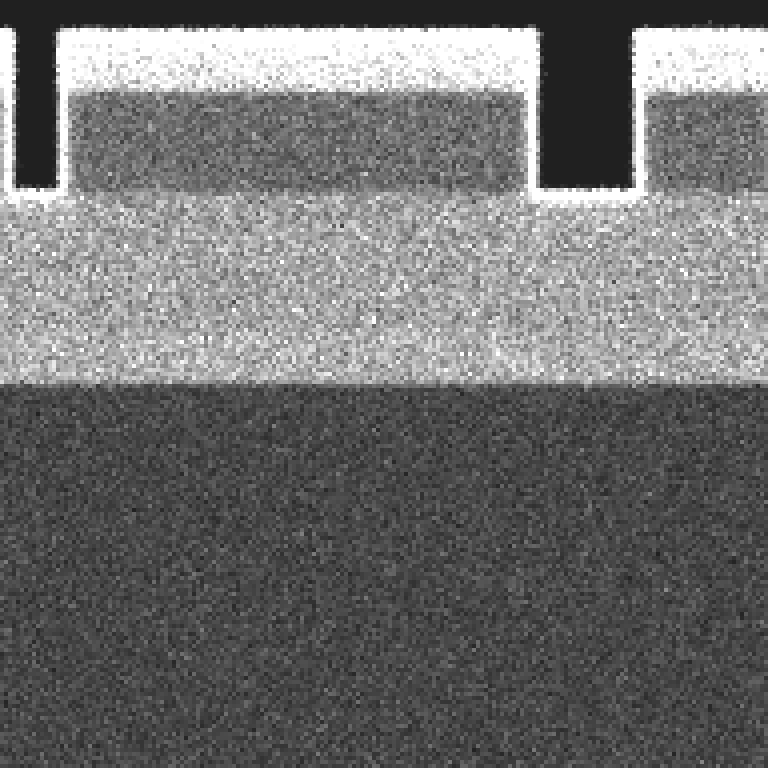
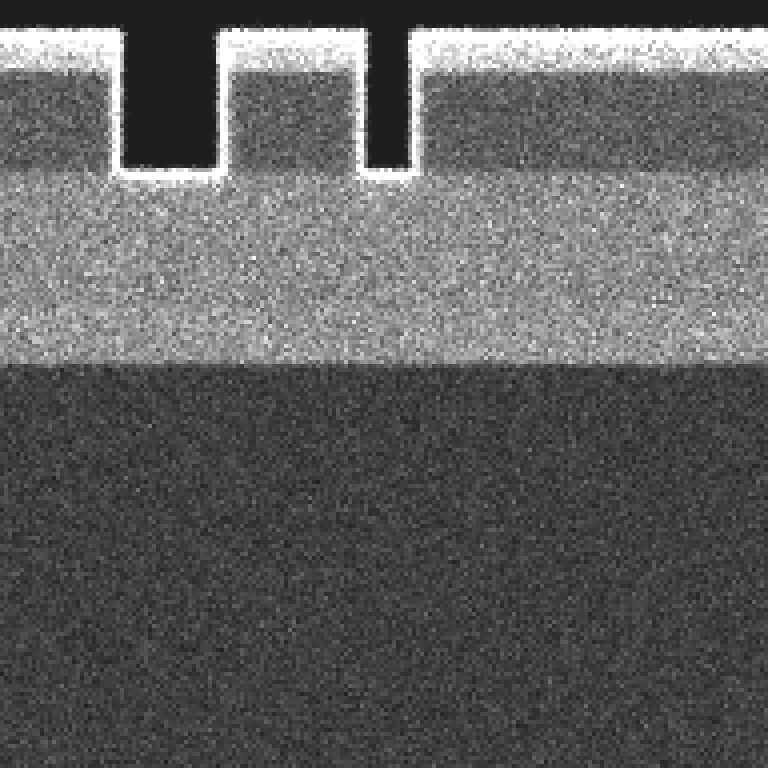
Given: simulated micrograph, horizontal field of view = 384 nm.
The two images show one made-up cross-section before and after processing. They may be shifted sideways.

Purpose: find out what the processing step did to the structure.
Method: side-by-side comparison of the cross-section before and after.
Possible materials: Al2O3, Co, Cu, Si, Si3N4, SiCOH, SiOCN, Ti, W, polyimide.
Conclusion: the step removed W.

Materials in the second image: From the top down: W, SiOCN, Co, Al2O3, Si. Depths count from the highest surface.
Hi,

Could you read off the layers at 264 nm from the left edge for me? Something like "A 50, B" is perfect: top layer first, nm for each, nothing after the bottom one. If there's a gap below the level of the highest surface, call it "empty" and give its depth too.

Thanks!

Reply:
W 20, SiOCN 50, Co 68, Al2O3 28, Si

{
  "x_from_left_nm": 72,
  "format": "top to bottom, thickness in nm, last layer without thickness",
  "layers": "empty 70, Co 68, Al2O3 28, Si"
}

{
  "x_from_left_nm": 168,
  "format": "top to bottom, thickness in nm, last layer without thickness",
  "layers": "W 20, SiOCN 50, Co 68, Al2O3 28, Si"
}